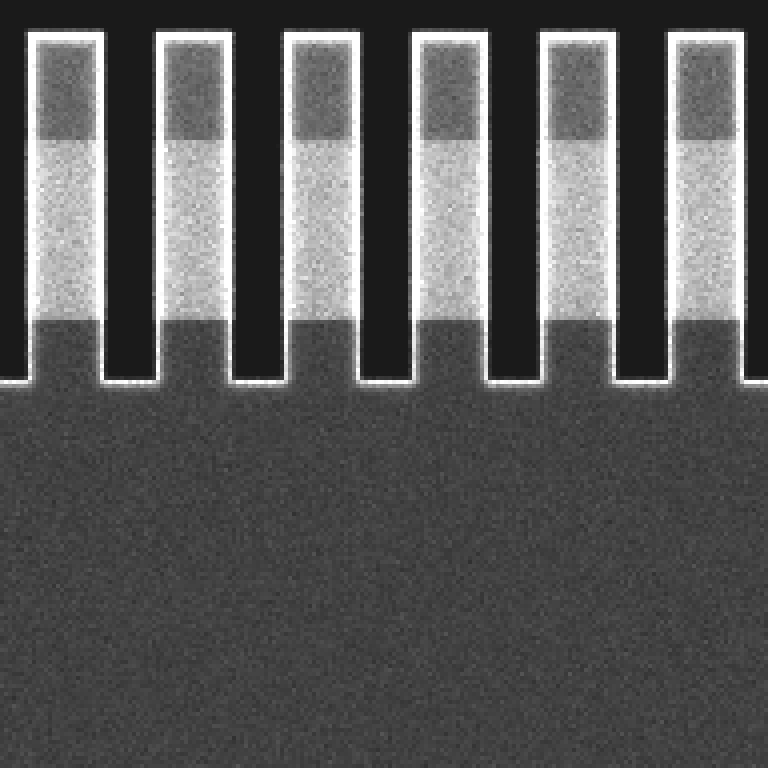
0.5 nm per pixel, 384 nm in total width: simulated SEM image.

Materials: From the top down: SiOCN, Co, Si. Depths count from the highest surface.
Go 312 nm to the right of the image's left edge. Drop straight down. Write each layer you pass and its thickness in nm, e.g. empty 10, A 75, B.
empty 174, Si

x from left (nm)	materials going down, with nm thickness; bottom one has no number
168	SiOCN 54, Co 90, Si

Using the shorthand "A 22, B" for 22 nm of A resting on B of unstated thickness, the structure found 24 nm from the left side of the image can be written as SiOCN 54, Co 90, Si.